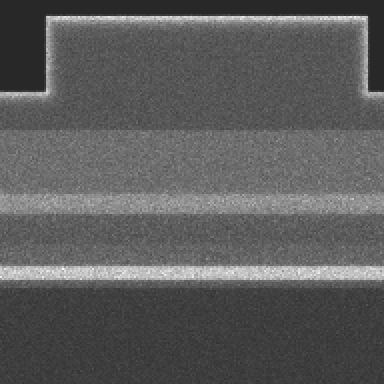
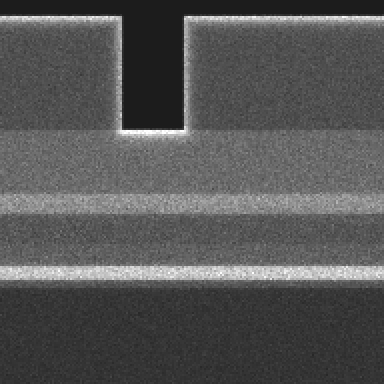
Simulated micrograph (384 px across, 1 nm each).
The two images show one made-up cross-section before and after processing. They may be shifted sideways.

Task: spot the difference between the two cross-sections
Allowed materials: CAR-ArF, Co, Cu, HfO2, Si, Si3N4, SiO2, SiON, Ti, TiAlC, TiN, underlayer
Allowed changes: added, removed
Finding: removed underlayer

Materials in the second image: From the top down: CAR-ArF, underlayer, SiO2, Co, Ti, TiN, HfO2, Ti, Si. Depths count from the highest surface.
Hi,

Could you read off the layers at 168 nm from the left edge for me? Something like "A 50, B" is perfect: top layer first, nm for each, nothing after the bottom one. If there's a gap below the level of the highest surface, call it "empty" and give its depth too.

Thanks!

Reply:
empty 114, SiO2 64, Co 20, Ti 30, TiN 22, HfO2 14, Ti 8, Si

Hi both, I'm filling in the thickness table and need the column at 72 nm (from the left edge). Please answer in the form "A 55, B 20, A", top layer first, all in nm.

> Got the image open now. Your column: CAR-ArF 76, underlayer 38, SiO2 64, Co 20, Ti 30, TiN 22, HfO2 14, Ti 8, Si